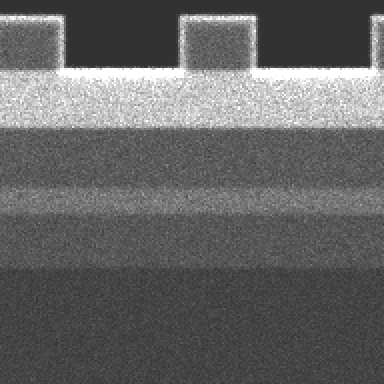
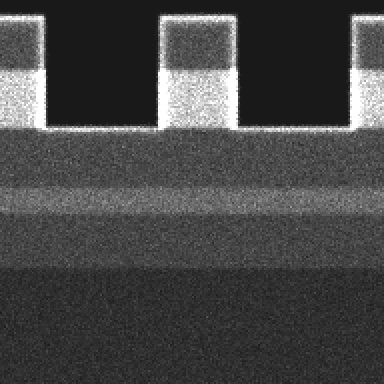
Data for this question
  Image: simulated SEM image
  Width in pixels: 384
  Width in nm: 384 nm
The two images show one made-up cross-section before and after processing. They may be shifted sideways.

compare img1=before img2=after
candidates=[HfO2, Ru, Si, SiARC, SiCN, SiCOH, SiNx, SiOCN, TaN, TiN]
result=removed:HfO2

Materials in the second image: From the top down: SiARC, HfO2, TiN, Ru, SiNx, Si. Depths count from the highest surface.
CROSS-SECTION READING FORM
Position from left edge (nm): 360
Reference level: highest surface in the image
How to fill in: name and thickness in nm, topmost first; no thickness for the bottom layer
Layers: SiARC 54, HfO2 58, TiN 60, Ru 26, SiNx 54, Si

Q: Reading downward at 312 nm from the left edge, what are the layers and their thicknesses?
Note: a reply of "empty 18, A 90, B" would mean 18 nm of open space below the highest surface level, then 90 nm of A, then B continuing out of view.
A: empty 112, TiN 60, Ru 26, SiNx 54, Si